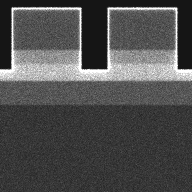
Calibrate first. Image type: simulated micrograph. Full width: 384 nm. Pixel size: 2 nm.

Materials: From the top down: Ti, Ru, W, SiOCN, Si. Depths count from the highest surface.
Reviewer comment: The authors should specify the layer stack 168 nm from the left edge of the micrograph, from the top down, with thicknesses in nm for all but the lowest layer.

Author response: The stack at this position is empty 124, W 22, SiOCN 48, Si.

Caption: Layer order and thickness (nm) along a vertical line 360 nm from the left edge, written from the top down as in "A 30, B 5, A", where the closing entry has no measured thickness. empty 124, W 22, SiOCN 48, Si